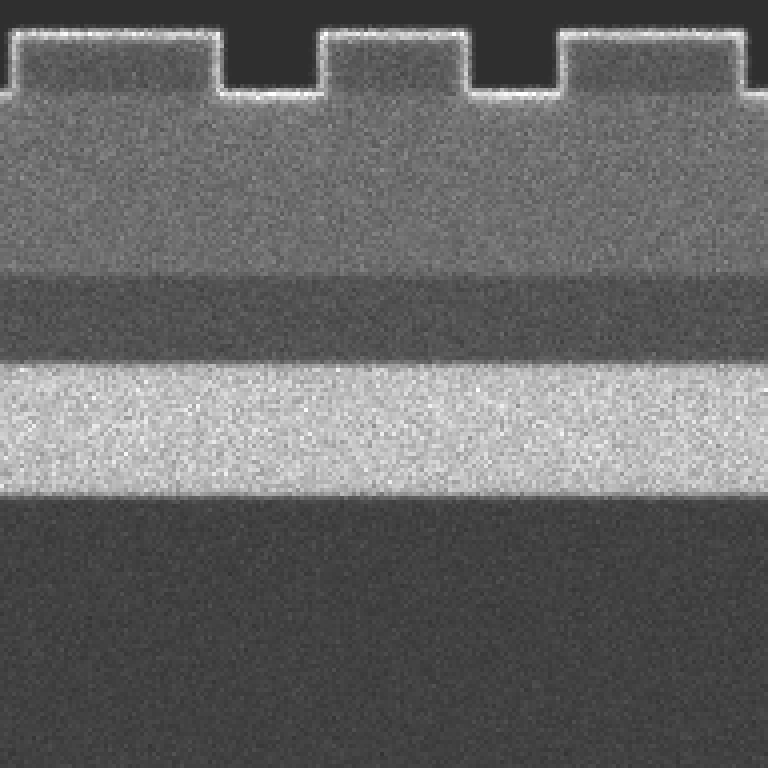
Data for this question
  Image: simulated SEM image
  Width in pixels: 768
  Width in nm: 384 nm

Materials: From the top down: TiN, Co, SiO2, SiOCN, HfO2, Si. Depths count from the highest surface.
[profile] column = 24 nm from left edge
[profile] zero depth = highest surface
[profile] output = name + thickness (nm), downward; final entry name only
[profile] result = TiN 30, Co 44, SiO2 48, SiOCN 44, HfO2 66, Si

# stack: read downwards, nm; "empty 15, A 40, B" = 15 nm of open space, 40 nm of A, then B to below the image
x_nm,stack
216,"TiN 30, Co 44, SiO2 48, SiOCN 44, HfO2 66, Si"